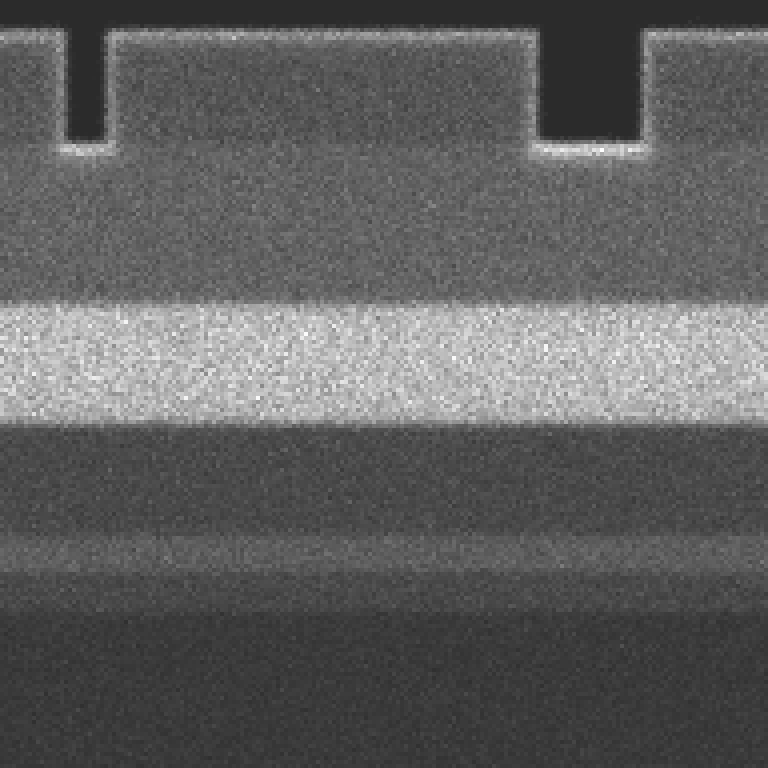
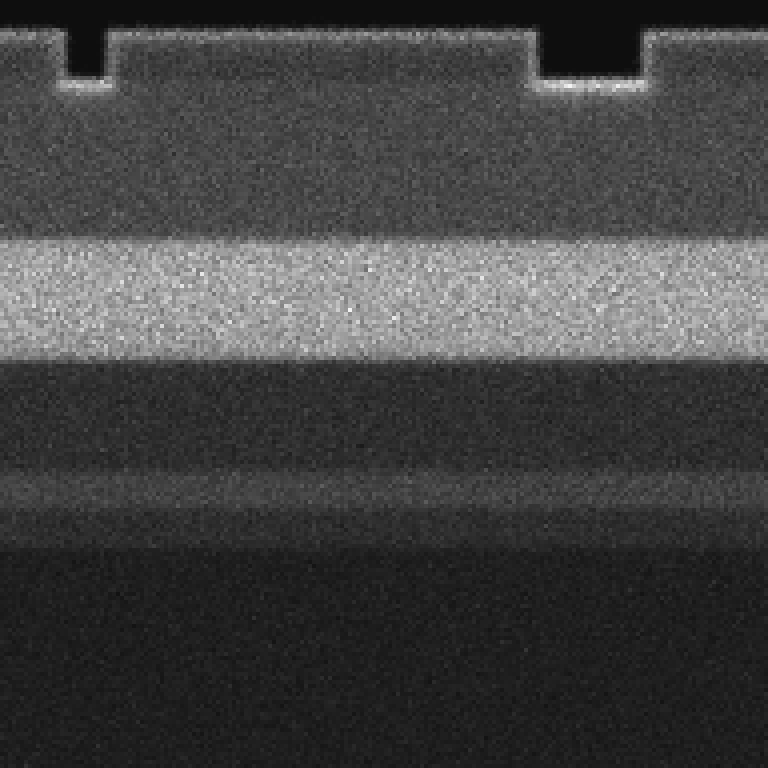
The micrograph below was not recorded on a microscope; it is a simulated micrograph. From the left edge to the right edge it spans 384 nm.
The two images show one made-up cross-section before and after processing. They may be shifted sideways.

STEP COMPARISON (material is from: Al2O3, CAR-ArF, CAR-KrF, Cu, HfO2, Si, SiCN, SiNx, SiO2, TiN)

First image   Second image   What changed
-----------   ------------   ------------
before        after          TiN, removed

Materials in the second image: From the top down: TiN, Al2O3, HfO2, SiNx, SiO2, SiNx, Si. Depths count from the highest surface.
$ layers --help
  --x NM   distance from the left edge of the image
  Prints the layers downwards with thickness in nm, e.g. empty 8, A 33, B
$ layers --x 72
TiN 24, Al2O3 80, HfO2 60, SiNx 56, SiO2 18, SiNx 20, Si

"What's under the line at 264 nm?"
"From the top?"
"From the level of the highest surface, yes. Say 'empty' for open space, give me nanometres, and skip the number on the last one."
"TiN 24, Al2O3 80, HfO2 60, SiNx 56, SiO2 18, SiNx 20, Si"